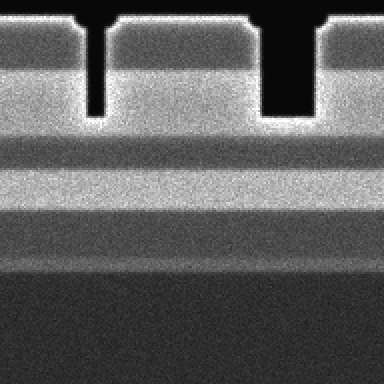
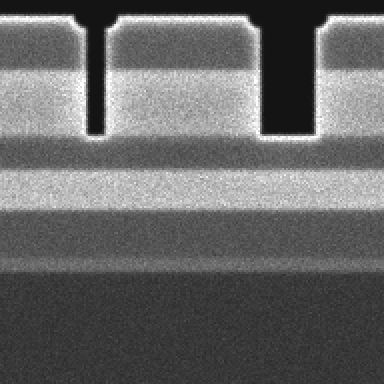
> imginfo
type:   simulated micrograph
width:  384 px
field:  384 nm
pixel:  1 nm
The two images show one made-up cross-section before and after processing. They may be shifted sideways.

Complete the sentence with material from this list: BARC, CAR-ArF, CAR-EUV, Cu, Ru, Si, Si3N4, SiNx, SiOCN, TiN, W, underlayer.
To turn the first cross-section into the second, Ru must be removed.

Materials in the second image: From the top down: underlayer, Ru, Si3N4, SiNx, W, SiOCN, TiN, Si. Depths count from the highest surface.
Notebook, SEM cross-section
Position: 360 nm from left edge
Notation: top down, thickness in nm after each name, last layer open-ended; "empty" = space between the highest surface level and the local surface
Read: underlayer 54, Ru 66, Si3N4 8, SiNx 26, W 40, SiOCN 48, TiN 14, Si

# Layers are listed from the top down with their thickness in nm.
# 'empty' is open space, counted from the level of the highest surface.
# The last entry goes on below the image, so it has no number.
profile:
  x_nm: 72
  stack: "underlayer 54, Ru 66, Si3N4 8, SiNx 26, W 40, SiOCN 48, TiN 14, Si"